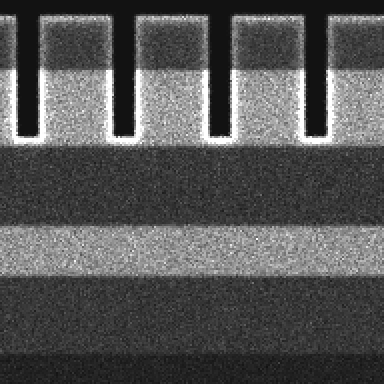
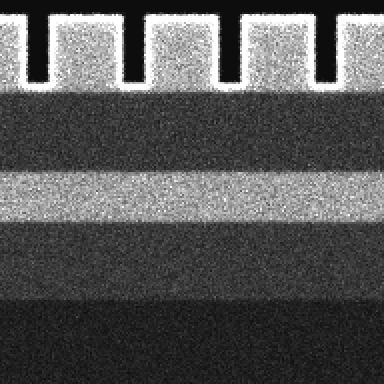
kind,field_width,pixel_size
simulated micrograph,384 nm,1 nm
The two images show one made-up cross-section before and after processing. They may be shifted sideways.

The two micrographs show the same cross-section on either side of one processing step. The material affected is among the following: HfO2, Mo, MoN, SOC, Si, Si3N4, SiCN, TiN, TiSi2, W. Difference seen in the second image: SOC removed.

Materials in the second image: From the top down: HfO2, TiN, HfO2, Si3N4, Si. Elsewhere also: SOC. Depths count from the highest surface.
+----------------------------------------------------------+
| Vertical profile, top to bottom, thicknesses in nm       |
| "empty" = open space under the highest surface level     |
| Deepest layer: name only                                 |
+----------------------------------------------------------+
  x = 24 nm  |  HfO2 76, TiN 80, HfO2 50, Si3N4 78, Si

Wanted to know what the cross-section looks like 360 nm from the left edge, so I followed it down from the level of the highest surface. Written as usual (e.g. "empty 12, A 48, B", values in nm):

HfO2 76, TiN 80, HfO2 50, Si3N4 78, Si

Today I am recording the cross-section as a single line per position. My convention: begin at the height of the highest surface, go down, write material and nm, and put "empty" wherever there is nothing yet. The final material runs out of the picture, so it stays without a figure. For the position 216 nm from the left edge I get HfO2 76, TiN 80, HfO2 50, Si3N4 78, Si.